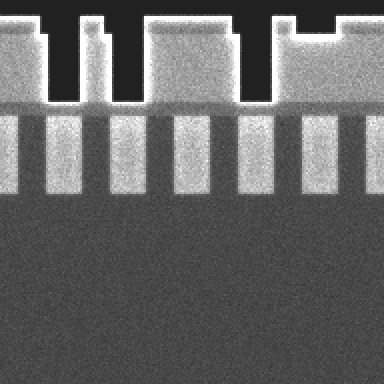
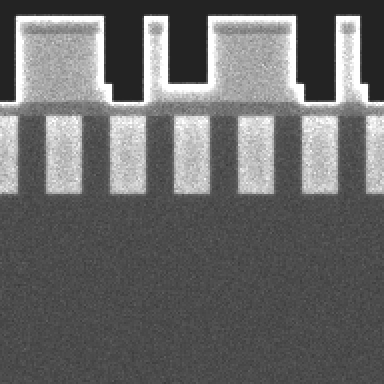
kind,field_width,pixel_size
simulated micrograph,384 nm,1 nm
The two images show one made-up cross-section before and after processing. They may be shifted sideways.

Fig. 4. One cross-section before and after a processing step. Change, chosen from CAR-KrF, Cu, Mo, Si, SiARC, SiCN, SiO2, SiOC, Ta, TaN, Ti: SiO2 removed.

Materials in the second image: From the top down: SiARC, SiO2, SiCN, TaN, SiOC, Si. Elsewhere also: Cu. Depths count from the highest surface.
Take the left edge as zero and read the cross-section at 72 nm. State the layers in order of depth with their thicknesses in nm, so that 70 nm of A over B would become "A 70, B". SiARC 18, SiO2 68, SiCN 14, TaN 78, SiOC 26, Si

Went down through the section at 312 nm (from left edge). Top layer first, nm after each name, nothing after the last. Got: empty 86, SiCN 14, Cu 68, TaN 10, SiOC 26, Si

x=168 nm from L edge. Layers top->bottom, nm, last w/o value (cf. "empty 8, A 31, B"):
empty 68, SiO2 18, SiCN 14, SiOC 104, Si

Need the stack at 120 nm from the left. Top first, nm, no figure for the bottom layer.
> empty 86, SiCN 14, Cu 68, TaN 10, SiOC 26, Si